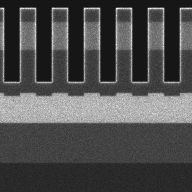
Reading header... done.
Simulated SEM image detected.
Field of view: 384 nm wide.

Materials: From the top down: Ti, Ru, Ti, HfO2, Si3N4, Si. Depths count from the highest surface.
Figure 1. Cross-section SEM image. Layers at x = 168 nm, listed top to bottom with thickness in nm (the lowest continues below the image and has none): Ti 28, Ru 56, Ti 86, HfO2 60, Si3N4 80, Si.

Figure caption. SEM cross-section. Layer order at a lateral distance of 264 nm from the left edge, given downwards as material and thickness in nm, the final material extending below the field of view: empty 148, Ti 28, HfO2 54, Si3N4 80, Si